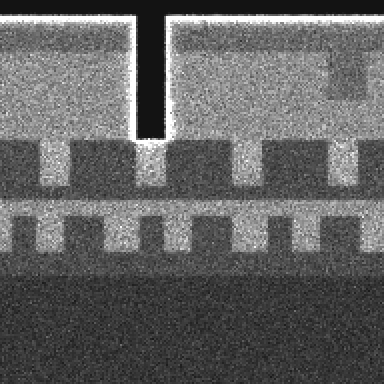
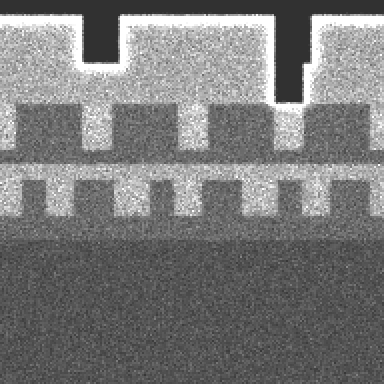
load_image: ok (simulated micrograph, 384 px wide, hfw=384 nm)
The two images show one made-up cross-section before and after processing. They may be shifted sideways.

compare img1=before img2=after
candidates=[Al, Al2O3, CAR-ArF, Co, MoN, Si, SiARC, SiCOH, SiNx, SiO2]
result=removed:SiARC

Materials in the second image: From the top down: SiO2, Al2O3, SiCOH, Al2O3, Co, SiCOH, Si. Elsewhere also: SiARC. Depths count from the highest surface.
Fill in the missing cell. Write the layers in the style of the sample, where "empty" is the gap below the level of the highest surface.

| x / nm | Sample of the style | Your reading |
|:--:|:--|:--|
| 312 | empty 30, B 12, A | SiO2 78, Al2O3 10, SiCOH 60, Al2O3 16, Co 36, SiCOH 24, Si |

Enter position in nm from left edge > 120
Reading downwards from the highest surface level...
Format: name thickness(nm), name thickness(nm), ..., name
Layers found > SiO2 78, Al2O3 10, SiCOH 60, Al2O3 16, Co 36, SiCOH 24, Si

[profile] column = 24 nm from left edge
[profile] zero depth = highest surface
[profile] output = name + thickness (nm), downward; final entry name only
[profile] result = SiO2 78, Al2O3 10, SiCOH 60, Al2O3 16, SiCOH 60, Si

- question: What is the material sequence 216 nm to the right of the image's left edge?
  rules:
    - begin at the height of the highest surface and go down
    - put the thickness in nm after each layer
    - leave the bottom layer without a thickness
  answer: SiO2 78, Al2O3 10, SiCOH 60, Al2O3 16, SiCOH 60, Si